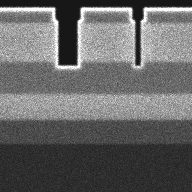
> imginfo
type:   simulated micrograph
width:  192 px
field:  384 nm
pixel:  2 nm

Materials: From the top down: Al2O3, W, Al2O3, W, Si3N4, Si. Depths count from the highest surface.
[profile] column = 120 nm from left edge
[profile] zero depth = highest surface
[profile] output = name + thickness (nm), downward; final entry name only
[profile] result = empty 116, Al2O3 56, W 52, Si3N4 48, Si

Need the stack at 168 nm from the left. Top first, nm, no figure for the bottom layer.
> Al2O3 30, W 78, Al2O3 64, W 52, Si3N4 48, Si